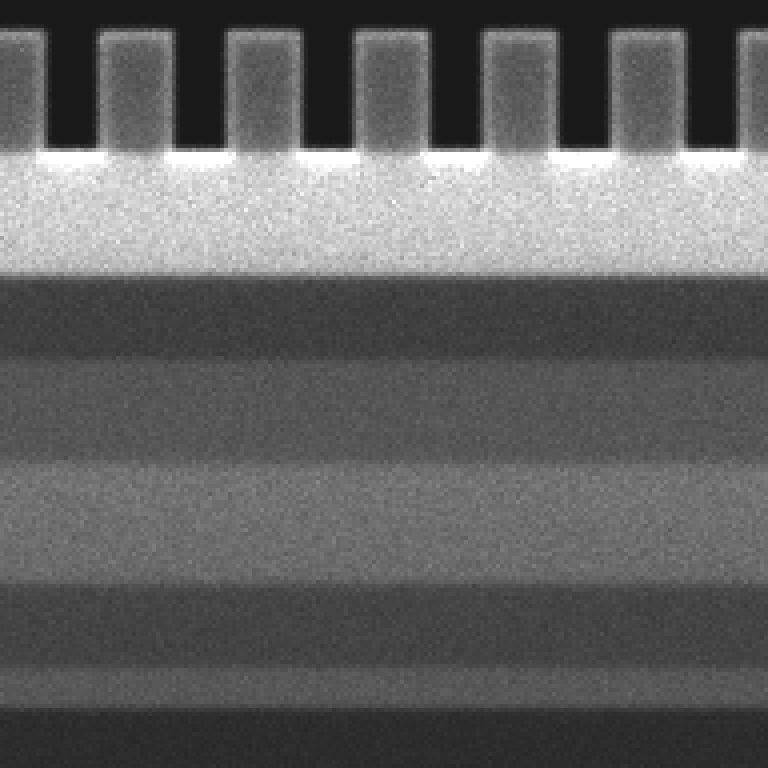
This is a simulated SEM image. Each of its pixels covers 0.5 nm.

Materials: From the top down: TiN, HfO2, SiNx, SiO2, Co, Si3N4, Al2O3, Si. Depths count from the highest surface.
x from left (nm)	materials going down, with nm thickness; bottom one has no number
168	empty 60, HfO2 62, SiNx 42, SiO2 52, Co 60, Si3N4 42, Al2O3 20, Si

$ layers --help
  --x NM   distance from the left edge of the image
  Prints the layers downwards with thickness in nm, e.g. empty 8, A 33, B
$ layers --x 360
empty 60, HfO2 62, SiNx 42, SiO2 52, Co 60, Si3N4 42, Al2O3 20, Si